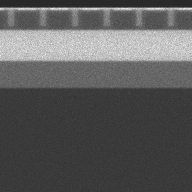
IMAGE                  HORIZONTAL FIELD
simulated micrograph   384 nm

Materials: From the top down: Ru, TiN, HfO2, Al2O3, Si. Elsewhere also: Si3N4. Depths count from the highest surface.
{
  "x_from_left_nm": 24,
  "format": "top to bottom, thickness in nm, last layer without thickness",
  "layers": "Ru 36, TiN 8, HfO2 62, Al2O3 54, Si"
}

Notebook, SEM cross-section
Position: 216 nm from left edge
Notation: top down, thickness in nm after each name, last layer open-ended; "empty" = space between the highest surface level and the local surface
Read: Ru 36, TiN 8, HfO2 62, Al2O3 54, Si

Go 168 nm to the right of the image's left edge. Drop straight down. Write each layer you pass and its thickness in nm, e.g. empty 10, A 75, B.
Si3N4 44, HfO2 62, Al2O3 54, Si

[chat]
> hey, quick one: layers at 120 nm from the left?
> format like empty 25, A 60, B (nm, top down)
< Si3N4 44, HfO2 62, Al2O3 54, Si